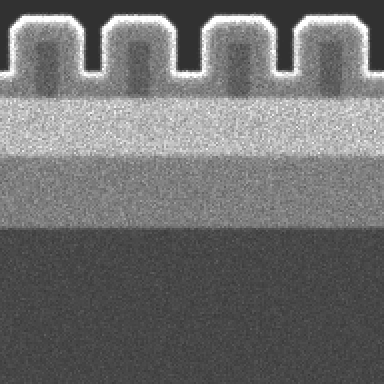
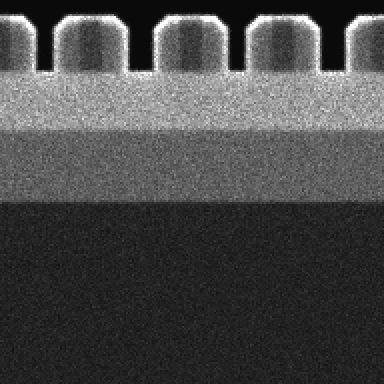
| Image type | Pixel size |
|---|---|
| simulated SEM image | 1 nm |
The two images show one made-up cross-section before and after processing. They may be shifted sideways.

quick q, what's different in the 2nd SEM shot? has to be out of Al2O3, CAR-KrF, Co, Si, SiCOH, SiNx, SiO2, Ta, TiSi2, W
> SiO2 removed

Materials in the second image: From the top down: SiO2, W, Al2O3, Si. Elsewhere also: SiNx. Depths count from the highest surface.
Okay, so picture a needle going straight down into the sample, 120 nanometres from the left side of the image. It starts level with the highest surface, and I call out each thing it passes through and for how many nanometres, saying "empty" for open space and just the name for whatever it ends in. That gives empty 6, SiO2 50, W 58, Al2O3 72, Si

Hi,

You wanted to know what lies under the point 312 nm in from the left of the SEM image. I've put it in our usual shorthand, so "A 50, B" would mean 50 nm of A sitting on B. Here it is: empty 6, SiO2 50, W 58, Al2O3 72, Si